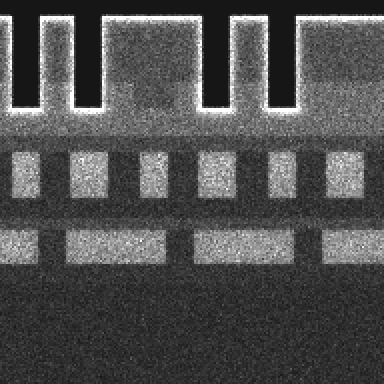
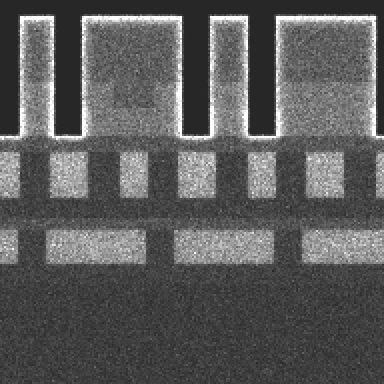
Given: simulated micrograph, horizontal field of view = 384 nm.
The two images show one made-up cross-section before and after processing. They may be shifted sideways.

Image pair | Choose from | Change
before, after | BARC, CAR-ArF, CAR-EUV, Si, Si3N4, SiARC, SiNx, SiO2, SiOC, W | SiO2 (removed)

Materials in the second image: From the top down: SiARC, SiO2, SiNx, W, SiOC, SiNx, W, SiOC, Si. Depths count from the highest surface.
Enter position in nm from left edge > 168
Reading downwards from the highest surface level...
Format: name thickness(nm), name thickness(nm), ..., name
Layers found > SiARC 66, SiO2 54, SiNx 16, SiOC 66, SiNx 12, SiOC 54, Si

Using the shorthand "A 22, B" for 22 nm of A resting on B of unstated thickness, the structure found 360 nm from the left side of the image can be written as SiARC 66, SiO2 54, SiNx 16, SiOC 66, SiNx 12, W 34, SiOC 20, Si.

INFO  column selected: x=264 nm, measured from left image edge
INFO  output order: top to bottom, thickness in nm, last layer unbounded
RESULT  empty 120, SiNx 16, W 46, SiOC 20, SiNx 12, W 34, SiOC 20, Si